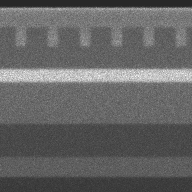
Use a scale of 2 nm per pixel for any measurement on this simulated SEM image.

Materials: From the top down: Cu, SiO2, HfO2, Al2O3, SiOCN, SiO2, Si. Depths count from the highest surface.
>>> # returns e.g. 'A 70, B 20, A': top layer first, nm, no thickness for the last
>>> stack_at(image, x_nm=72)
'Cu 38, SiO2 84, HfO2 26, Al2O3 84, SiOCN 66, SiO2 40, Si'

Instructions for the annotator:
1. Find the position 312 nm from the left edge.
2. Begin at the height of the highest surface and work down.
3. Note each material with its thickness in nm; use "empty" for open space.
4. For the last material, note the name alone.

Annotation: Cu 38, SiO2 84, HfO2 26, Al2O3 84, SiOCN 66, SiO2 40, Si